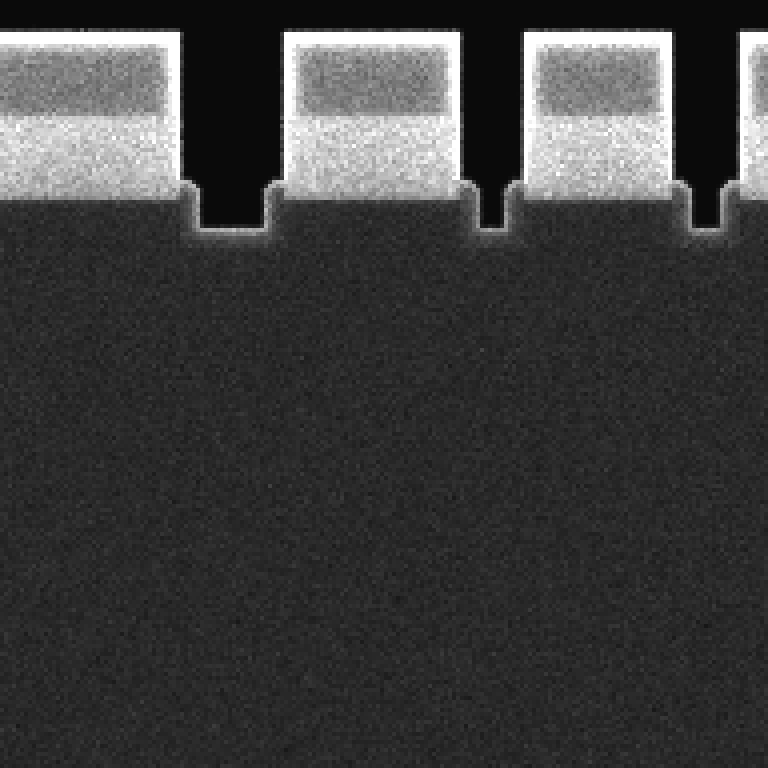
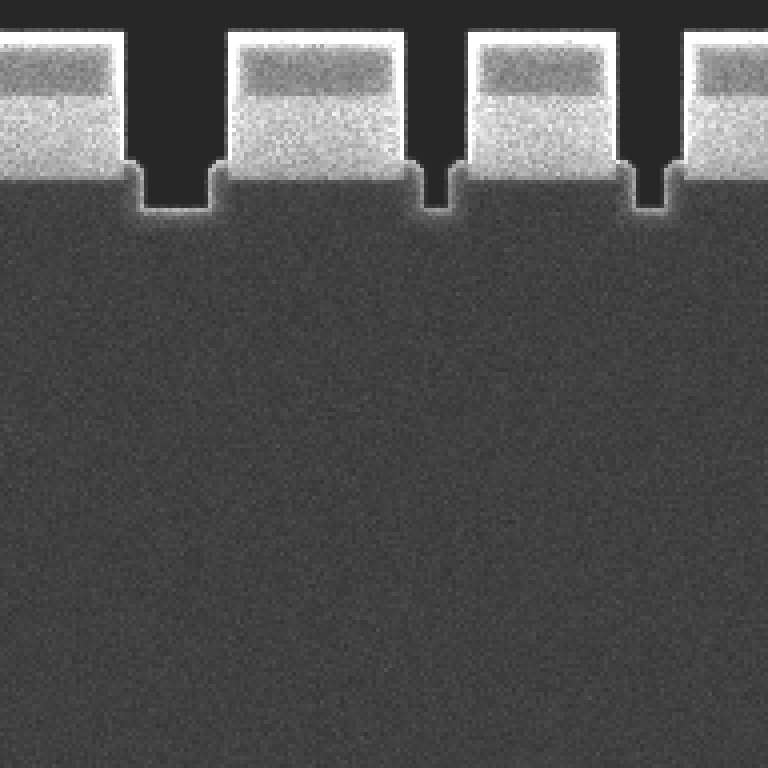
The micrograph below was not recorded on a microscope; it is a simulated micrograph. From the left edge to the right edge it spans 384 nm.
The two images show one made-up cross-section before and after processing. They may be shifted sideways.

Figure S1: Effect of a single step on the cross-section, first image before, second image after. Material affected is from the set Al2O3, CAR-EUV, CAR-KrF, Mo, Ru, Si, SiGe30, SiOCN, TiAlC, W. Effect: removed Al2O3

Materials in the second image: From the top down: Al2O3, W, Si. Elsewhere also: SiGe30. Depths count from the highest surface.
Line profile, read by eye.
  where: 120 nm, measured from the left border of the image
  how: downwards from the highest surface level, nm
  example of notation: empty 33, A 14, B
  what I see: Al2O3 32, W 42, Si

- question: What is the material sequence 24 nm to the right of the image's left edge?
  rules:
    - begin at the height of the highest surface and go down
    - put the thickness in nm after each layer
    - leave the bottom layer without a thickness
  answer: Al2O3 32, W 42, Si